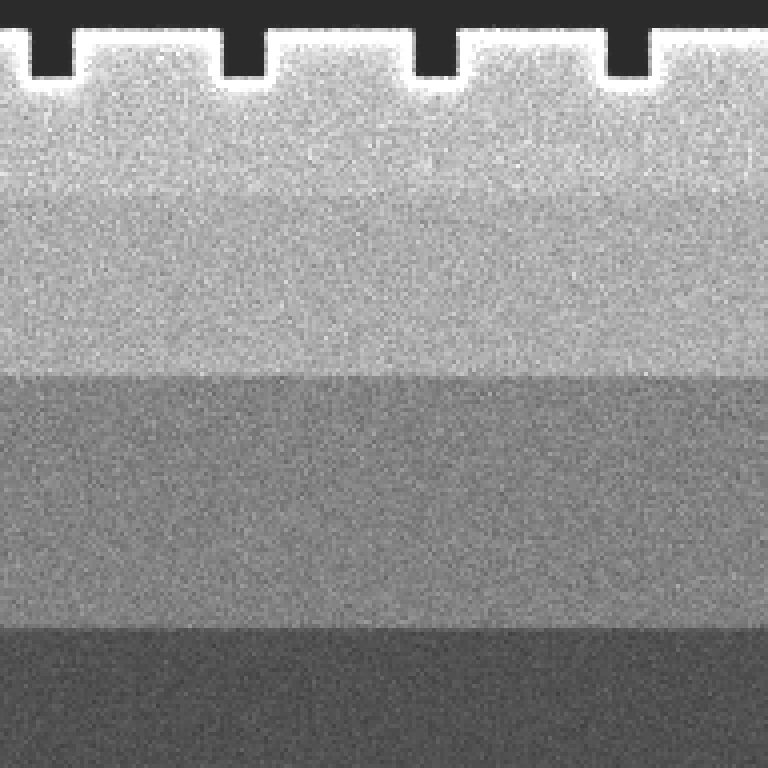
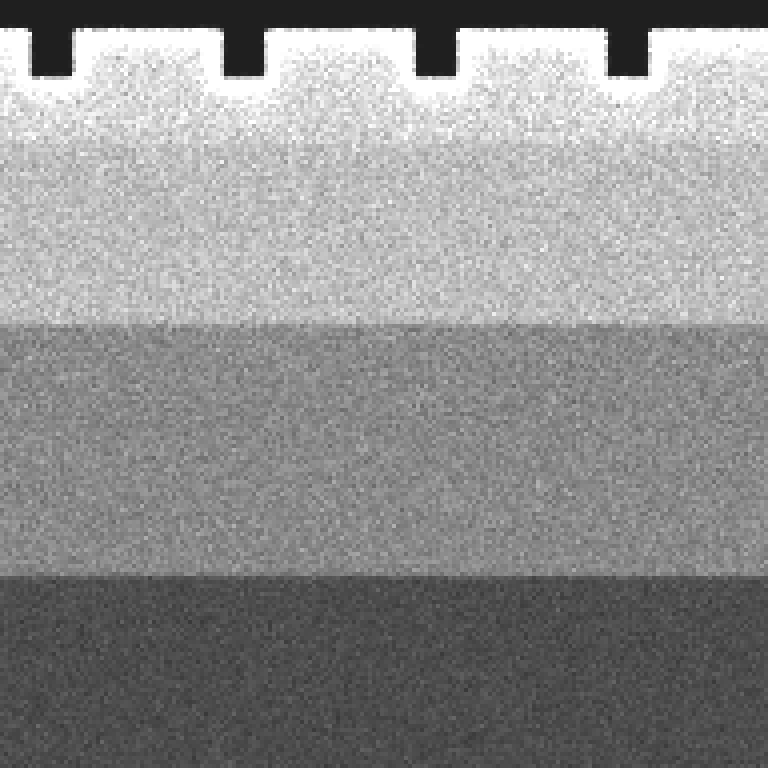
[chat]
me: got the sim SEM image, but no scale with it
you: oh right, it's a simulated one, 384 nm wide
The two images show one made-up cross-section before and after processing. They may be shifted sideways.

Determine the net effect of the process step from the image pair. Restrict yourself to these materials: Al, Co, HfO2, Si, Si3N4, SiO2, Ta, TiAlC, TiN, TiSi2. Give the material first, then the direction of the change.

Co: removed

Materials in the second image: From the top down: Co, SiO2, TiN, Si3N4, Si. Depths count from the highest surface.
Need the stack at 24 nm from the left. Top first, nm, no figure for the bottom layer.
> empty 24, Co 32, SiO2 90, TiN 54, Si3N4 72, Si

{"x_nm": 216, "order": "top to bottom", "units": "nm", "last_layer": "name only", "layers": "empty 24, Co 32, SiO2 90, TiN 54, Si3N4 72, Si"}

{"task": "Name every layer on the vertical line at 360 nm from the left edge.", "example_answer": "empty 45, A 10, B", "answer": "Co 56, SiO2 90, TiN 54, Si3N4 72, Si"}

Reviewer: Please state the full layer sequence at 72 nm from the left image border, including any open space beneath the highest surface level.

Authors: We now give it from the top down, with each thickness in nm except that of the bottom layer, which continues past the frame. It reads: Co 56, SiO2 90, TiN 54, Si3N4 72, Si